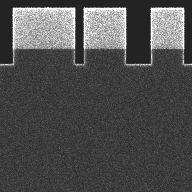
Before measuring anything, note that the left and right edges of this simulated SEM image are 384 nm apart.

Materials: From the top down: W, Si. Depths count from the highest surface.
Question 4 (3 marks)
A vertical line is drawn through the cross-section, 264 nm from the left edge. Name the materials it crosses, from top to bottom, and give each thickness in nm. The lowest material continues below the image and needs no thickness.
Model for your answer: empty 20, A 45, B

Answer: empty 112, Si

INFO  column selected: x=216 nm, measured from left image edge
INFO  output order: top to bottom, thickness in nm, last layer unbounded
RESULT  W 82, Si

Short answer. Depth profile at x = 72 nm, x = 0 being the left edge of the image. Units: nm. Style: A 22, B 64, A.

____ W 82, Si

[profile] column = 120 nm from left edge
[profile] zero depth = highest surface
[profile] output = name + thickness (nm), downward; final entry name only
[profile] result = W 82, Si